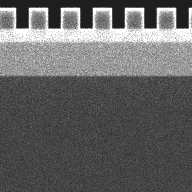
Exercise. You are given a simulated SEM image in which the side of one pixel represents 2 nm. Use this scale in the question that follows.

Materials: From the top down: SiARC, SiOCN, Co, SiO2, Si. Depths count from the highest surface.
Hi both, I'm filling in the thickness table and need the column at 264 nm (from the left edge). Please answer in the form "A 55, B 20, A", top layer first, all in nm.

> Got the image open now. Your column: SiARC 16, SiOCN 26, Co 26, SiO2 68, Si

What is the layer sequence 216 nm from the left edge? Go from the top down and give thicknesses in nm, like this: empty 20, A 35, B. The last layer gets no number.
SiARC 16, SiOCN 26, Co 26, SiO2 68, Si